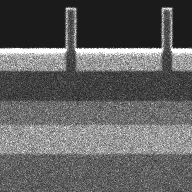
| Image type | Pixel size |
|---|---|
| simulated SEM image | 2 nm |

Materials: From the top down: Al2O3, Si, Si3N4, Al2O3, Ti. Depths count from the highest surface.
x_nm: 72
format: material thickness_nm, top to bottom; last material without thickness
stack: empty 82, Al2O3 44, Si 60, Si3N4 48, Al2O3 58, Ti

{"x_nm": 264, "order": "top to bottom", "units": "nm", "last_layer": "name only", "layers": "empty 82, Al2O3 44, Si 60, Si3N4 48, Al2O3 58, Ti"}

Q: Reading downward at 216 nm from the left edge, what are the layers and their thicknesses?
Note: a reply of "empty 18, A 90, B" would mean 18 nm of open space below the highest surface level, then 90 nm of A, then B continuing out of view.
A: empty 82, Al2O3 44, Si 60, Si3N4 48, Al2O3 58, Ti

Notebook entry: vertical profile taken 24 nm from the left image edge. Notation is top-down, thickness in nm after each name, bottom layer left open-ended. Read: empty 82, Al2O3 44, Si 60, Si3N4 48, Al2O3 58, Ti